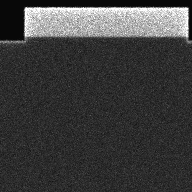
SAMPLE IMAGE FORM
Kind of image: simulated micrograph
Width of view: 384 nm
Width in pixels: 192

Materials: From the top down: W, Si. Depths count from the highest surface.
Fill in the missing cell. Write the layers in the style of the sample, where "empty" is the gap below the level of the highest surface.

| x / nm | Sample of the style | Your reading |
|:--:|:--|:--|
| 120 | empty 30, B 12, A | W 58, Si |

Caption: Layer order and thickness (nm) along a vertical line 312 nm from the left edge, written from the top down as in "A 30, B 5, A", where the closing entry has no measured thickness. W 58, Si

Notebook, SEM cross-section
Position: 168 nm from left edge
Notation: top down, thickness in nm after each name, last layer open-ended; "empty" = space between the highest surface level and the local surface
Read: W 58, Si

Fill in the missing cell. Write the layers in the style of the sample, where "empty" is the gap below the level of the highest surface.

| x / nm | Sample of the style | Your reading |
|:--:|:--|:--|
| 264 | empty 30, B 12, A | W 58, Si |